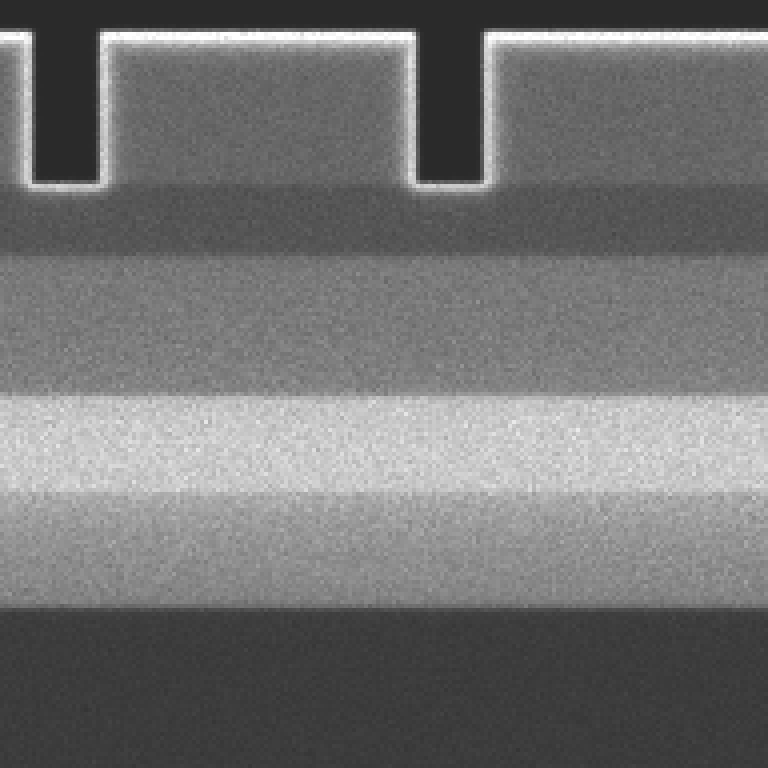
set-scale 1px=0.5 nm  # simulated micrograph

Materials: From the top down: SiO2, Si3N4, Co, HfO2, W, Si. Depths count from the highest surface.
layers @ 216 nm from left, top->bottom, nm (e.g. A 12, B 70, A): empty 76, Si3N4 36, Co 70, HfO2 48, W 58, Si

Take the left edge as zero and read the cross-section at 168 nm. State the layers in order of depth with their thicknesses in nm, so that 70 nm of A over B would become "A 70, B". SiO2 76, Si3N4 36, Co 70, HfO2 48, W 58, Si